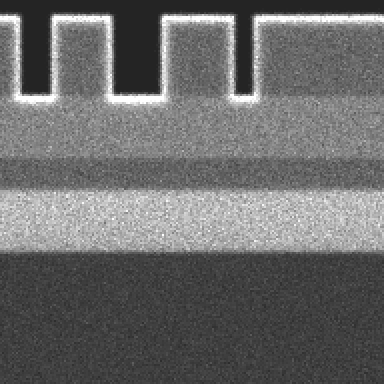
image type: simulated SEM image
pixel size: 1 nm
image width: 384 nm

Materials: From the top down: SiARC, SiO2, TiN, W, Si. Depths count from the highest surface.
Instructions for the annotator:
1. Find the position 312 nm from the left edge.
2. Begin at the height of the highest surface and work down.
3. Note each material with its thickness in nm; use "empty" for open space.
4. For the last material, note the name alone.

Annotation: SiARC 80, SiO2 62, TiN 32, W 62, Si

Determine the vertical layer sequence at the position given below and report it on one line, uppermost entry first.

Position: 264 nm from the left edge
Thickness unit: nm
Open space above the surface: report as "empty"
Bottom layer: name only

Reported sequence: SiARC 80, SiO2 62, TiN 32, W 62, Si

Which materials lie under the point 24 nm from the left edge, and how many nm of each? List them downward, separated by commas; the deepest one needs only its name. empty 80, SiO2 62, TiN 32, W 62, Si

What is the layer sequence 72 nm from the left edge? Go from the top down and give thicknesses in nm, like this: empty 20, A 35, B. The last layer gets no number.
SiARC 80, SiO2 62, TiN 32, W 62, Si